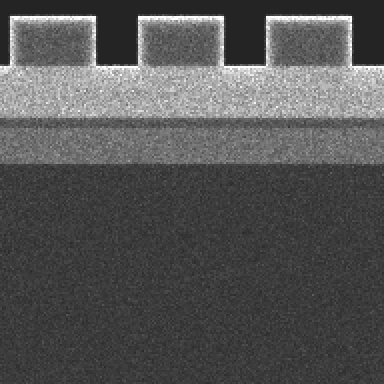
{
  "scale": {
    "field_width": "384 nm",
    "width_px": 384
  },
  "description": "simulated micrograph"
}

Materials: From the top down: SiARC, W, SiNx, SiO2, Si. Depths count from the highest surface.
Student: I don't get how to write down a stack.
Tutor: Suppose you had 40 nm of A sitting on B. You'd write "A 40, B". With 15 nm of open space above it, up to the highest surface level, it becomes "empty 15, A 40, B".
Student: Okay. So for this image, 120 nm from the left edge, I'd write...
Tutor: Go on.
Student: empty 50, W 52, SiNx 10, SiO2 36, Si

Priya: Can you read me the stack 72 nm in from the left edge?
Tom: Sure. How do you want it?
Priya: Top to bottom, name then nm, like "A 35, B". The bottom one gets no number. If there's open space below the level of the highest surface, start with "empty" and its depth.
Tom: SiARC 50, W 52, SiNx 10, SiO2 36, Si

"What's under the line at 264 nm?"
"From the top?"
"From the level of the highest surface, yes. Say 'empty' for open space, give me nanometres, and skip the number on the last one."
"empty 50, W 52, SiNx 10, SiO2 36, Si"